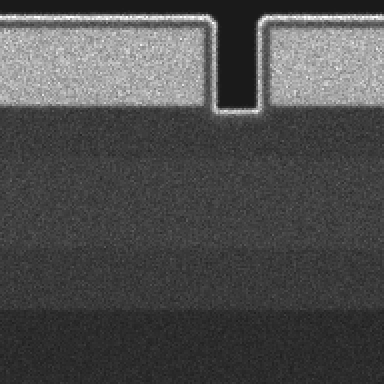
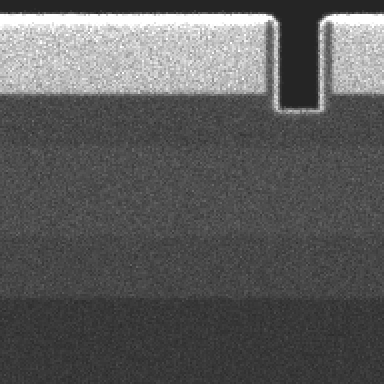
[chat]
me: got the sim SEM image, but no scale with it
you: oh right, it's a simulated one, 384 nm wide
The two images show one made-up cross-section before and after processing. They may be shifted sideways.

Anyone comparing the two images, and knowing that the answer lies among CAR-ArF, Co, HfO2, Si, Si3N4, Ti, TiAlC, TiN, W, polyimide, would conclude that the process removed Si3N4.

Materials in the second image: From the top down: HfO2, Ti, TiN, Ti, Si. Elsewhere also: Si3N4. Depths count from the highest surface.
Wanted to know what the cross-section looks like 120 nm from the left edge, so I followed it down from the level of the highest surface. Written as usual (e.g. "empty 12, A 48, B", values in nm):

HfO2 78, Ti 52, TiN 90, Ti 62, Si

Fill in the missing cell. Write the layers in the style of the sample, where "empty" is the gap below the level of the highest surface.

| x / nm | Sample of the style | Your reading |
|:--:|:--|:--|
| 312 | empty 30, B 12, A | empty 94, Ti 36, TiN 90, Ti 62, Si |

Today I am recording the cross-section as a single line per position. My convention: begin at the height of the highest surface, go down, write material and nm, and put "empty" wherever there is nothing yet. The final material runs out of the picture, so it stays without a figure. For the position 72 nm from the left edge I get HfO2 78, Ti 52, TiN 90, Ti 62, Si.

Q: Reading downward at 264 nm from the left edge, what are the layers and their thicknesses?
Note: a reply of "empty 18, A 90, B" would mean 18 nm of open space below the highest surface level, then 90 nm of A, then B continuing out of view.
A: HfO2 78, Ti 52, TiN 90, Ti 62, Si